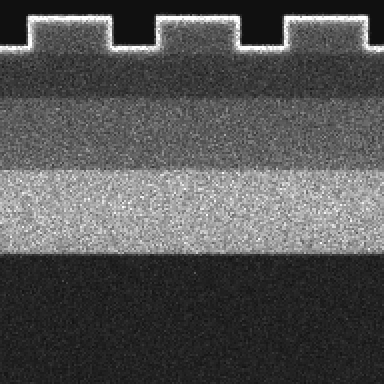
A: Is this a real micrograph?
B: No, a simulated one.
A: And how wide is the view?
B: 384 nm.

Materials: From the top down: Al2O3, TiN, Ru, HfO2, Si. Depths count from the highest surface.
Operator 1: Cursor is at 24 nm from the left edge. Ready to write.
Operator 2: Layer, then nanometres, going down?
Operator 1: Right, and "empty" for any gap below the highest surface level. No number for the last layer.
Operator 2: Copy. empty 30, Al2O3 8, TiN 44, Ru 72, HfO2 84, Si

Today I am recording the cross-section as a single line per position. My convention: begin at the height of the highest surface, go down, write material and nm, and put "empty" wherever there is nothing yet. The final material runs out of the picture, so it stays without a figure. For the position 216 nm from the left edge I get Al2O3 38, TiN 44, Ru 72, HfO2 84, Si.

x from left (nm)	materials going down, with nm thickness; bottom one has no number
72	Al2O3 38, TiN 44, Ru 72, HfO2 84, Si